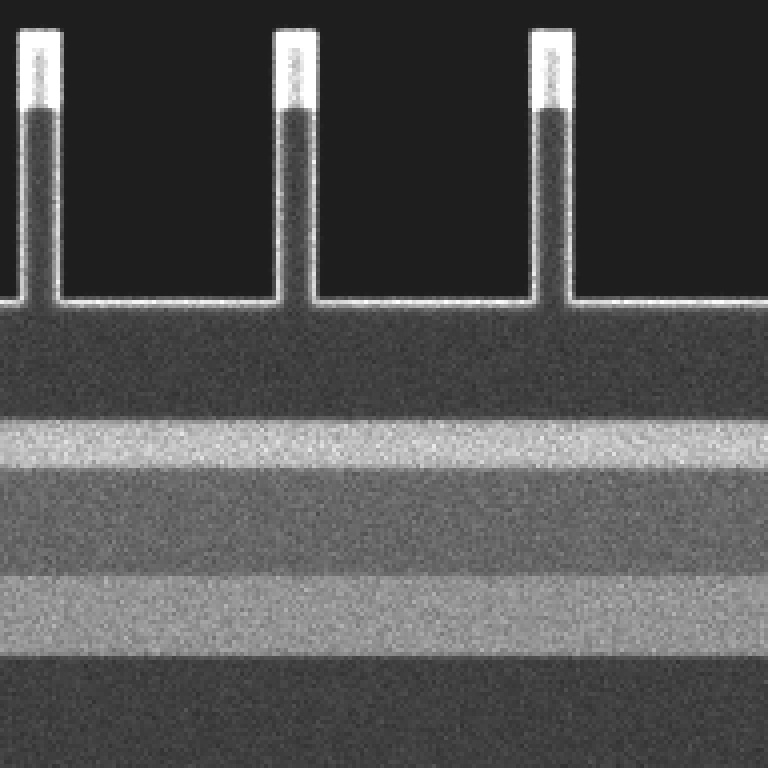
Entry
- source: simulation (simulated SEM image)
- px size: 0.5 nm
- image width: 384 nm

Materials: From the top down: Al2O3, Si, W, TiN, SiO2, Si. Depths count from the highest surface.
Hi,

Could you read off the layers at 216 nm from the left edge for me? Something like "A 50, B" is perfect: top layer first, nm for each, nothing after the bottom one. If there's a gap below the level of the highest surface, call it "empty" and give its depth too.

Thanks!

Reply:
empty 134, Si 60, W 24, TiN 54, SiO2 40, Si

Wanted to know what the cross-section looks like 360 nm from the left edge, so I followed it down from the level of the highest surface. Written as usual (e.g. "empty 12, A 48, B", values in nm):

empty 134, Si 60, W 24, TiN 54, SiO2 40, Si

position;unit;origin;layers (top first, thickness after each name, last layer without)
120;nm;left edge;empty 134, Si 60, W 24, TiN 54, SiO2 40, Si